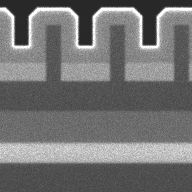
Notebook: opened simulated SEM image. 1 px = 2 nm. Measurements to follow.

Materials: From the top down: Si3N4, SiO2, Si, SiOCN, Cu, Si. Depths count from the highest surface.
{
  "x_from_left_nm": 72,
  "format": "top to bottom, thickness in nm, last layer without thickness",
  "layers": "empty 2, Si3N4 108, SiO2 36, Si 60, SiOCN 64, Cu 40, Si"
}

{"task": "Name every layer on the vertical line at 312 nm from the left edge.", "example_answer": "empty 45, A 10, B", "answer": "empty 76, Si3N4 34, SiO2 36, Si 60, SiOCN 64, Cu 40, Si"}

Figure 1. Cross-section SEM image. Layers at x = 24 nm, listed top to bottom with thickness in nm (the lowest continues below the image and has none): empty 14, Si3N4 96, SiO2 36, Si 60, SiOCN 64, Cu 40, Si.